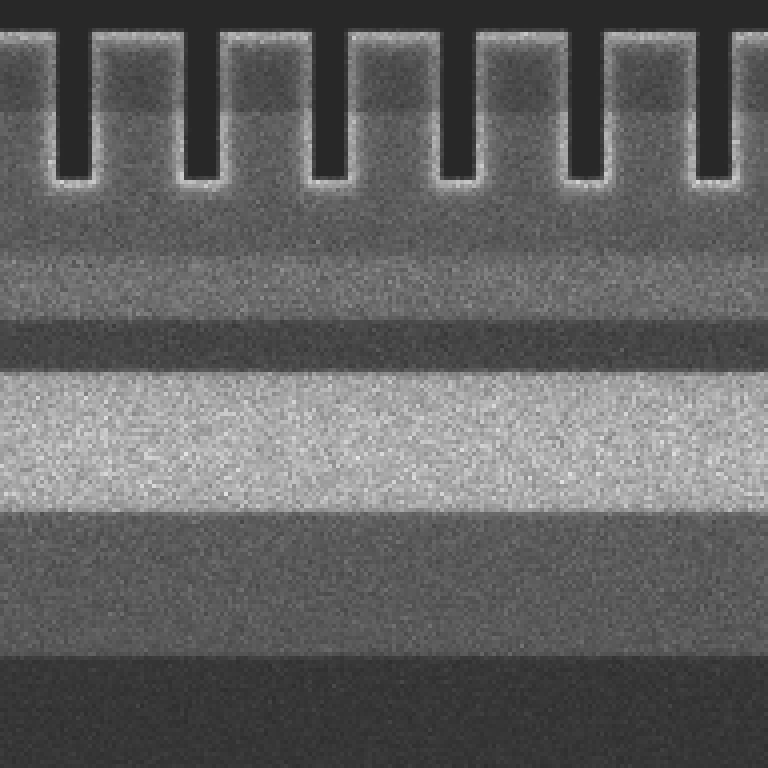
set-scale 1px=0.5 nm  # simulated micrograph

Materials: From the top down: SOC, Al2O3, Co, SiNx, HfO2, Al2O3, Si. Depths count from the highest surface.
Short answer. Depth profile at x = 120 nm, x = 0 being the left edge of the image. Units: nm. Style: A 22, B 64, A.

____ SOC 40, Al2O3 72, Co 32, SiNx 26, HfO2 70, Al2O3 72, Si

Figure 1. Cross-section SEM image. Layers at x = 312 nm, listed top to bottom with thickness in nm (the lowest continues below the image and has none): SOC 40, Al2O3 72, Co 32, SiNx 26, HfO2 70, Al2O3 72, Si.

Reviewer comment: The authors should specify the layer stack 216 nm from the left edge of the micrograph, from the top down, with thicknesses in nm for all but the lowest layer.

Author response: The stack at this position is SOC 40, Al2O3 72, Co 32, SiNx 26, HfO2 70, Al2O3 72, Si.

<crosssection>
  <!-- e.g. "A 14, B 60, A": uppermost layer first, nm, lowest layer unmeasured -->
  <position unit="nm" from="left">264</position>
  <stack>SOC 40, Al2O3 72, Co 32, SiNx 26, HfO2 70, Al2O3 72, Si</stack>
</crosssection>